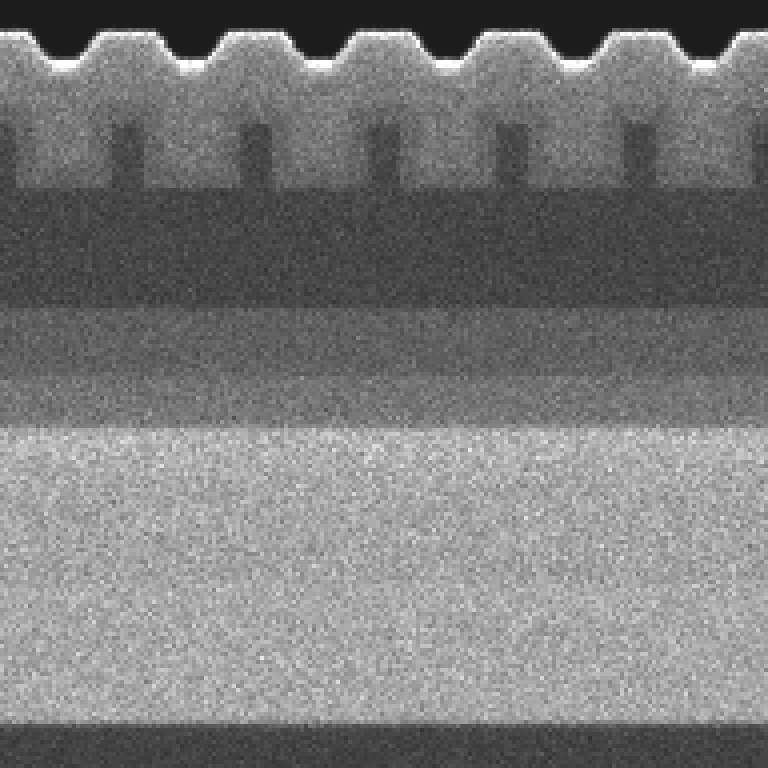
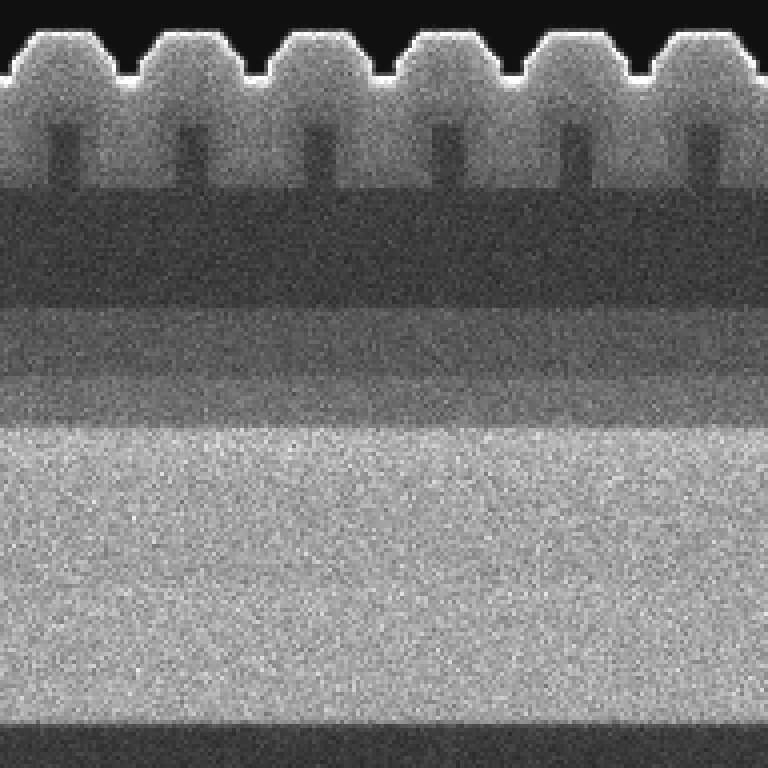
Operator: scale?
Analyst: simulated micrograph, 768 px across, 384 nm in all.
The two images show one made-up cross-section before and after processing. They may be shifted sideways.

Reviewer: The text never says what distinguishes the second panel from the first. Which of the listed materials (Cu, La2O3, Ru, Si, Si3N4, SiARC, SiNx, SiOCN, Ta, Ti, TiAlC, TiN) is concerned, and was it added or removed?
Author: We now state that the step removed SiARC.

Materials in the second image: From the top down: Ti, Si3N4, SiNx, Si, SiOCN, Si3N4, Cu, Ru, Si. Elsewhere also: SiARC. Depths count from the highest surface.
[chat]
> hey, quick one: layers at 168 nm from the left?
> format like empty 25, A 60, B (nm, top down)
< Ti 22, Si3N4 14, SiNx 42, Si 60, SiOCN 34, Si3N4 26, Cu 78, Ru 70, Si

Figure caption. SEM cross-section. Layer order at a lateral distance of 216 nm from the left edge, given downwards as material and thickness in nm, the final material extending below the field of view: Ti 22, Si3N4 14, SiNx 10, Si 92, SiOCN 34, Si3N4 26, Cu 78, Ru 70, Si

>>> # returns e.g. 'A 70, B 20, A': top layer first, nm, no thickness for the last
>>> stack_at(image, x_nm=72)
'empty 12, Ti 22, Si3N4 34, SiNx 10, Si 60, SiOCN 34, Si3N4 26, Cu 78, Ru 70, Si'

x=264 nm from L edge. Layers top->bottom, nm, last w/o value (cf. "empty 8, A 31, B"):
empty 12, Ti 22, Si3N4 34, SiNx 10, Si 60, SiOCN 34, Si3N4 26, Cu 78, Ru 70, Si